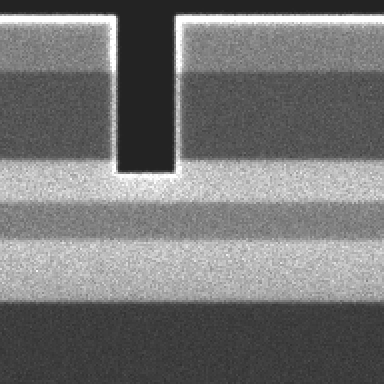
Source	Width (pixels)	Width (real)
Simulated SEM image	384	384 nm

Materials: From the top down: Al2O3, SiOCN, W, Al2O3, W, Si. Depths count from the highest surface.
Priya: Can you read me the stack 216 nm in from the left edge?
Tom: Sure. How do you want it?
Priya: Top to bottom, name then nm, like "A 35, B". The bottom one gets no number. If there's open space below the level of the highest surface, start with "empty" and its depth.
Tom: Al2O3 56, SiOCN 88, W 42, Al2O3 38, W 62, Si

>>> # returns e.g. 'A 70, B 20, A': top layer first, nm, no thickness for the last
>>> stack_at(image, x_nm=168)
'empty 158, W 28, Al2O3 38, W 62, Si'